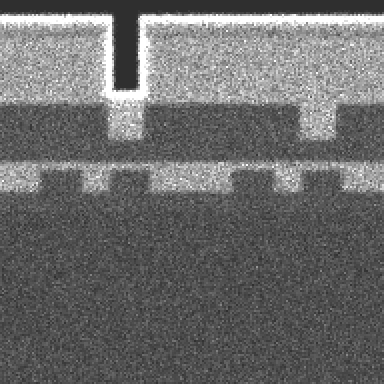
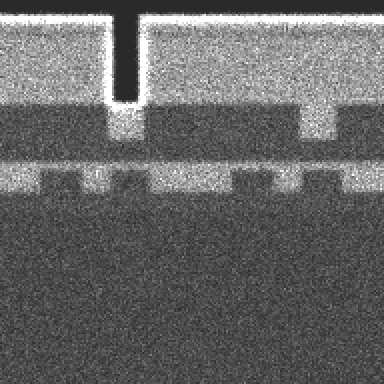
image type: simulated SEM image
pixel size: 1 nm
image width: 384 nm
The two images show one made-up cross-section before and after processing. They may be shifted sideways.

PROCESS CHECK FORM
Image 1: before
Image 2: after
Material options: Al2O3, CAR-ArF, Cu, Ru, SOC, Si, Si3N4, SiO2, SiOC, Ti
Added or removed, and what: removed, Al2O3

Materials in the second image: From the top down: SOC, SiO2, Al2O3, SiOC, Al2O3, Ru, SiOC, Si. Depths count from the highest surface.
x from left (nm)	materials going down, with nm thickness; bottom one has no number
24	SOC 22, SiO2 54, Al2O3 12, SiOC 58, Al2O3 8, Ru 22, SiOC 20, Si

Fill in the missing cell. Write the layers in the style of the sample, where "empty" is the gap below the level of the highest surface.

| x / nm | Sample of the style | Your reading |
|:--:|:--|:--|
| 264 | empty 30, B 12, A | SOC 22, SiO2 54, Al2O3 12, SiOC 58, Al2O3 8, SiOC 42, Si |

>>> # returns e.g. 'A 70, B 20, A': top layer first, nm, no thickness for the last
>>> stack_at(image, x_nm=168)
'SOC 22, SiO2 54, Al2O3 12, SiOC 58, Al2O3 8, Ru 22, SiOC 20, Si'